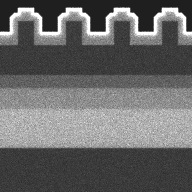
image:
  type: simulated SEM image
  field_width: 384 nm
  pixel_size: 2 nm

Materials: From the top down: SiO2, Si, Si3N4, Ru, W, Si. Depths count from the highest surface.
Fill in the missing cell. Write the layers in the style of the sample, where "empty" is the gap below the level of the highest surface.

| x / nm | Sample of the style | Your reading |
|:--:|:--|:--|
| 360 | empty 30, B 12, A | empty 10, SiO2 64, Si 60, Si3N4 26, Ru 42, W 78, Si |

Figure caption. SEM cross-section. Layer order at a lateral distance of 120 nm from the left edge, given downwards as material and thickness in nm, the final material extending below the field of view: empty 14, SiO2 60, Si 60, Si3N4 26, Ru 42, W 78, Si